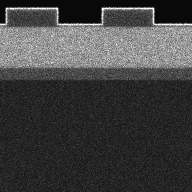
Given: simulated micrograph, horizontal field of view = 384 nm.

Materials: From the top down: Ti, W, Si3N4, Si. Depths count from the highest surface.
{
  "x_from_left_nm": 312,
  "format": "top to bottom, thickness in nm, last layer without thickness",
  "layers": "empty 32, Ti 6, W 82, Si3N4 24, Si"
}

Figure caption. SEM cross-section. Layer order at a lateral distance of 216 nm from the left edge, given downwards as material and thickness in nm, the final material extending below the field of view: Ti 38, W 82, Si3N4 24, Si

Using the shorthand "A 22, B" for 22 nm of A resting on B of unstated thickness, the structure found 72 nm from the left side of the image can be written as Ti 38, W 82, Si3N4 24, Si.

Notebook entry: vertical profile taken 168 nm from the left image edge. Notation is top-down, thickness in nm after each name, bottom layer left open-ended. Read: empty 32, Ti 6, W 82, Si3N4 24, Si